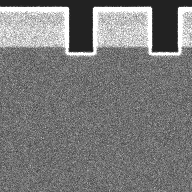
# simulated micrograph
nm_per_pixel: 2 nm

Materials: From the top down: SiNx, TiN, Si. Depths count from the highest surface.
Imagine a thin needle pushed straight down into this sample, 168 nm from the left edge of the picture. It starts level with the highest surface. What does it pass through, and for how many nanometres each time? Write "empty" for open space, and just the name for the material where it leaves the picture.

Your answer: empty 90, Si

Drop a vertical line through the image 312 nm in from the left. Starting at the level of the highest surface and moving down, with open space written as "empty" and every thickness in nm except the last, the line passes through empty 90, Si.